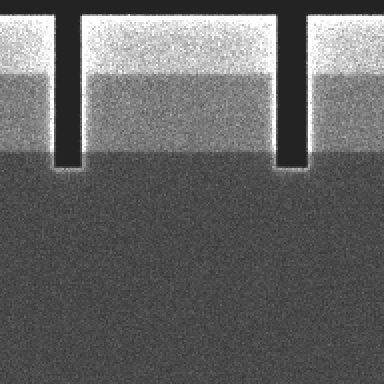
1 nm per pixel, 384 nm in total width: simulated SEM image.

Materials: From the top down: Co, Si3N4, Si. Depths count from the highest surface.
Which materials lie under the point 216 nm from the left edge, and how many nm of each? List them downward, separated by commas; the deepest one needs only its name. Co 58, Si3N4 78, Si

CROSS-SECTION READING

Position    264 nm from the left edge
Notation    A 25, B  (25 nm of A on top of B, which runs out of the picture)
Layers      Co 58, Si3N4 78, Si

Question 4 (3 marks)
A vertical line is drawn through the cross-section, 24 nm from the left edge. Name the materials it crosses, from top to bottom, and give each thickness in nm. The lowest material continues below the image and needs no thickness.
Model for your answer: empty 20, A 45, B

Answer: Co 58, Si3N4 78, Si